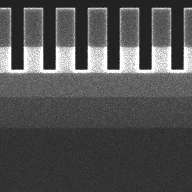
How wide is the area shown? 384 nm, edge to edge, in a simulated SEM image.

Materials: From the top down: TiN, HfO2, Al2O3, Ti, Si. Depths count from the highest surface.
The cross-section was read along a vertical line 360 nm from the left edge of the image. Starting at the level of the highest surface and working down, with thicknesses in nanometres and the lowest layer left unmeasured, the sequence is empty 124, HfO2 6, Al2O3 48, Ti 62, Si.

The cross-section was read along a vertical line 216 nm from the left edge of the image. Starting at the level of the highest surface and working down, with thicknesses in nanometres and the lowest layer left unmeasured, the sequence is empty 124, HfO2 6, Al2O3 48, Ti 62, Si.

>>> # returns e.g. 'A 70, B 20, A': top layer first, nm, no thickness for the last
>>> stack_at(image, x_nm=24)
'empty 124, HfO2 6, Al2O3 48, Ti 62, Si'